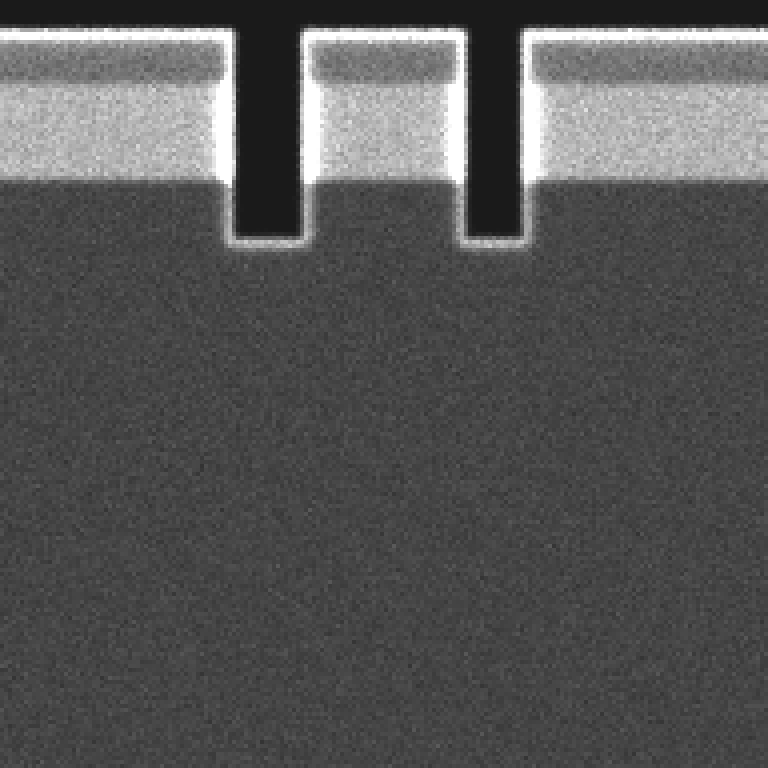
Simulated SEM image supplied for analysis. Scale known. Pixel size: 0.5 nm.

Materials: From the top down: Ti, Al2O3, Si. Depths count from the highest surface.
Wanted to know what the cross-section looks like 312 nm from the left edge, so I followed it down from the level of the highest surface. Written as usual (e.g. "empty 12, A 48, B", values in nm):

Ti 26, Al2O3 48, Si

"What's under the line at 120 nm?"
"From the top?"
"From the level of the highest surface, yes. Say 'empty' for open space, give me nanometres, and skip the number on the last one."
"empty 104, Si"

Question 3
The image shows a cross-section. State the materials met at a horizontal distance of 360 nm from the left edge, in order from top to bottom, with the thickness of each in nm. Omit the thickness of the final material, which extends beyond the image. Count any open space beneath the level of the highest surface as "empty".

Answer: Ti 26, Al2O3 48, Si